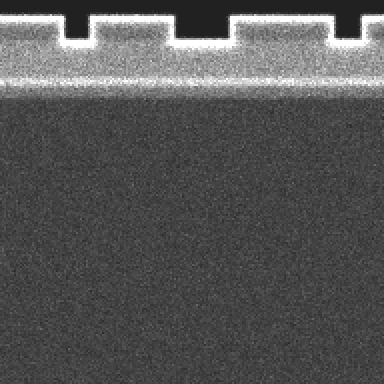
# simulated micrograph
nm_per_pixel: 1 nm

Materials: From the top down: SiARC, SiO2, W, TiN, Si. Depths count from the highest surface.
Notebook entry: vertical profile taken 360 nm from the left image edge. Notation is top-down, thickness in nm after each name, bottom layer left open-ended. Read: empty 24, SiO2 38, W 8, TiN 12, Si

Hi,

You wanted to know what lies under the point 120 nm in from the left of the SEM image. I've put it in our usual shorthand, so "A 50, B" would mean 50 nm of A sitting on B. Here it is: SiARC 24, SiO2 38, W 8, TiN 12, Si